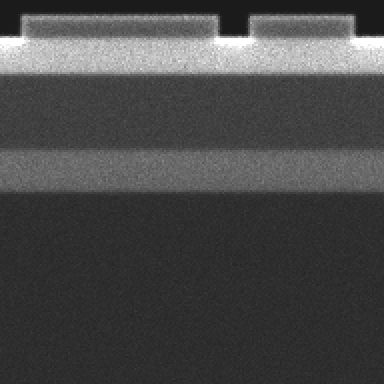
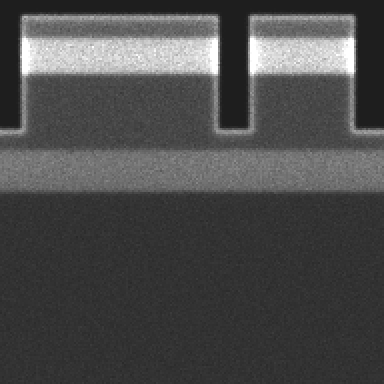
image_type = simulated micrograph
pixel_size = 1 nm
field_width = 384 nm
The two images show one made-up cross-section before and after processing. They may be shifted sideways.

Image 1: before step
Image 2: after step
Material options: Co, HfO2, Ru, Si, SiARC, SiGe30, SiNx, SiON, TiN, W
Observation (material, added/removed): HfO2 and SiNx, removed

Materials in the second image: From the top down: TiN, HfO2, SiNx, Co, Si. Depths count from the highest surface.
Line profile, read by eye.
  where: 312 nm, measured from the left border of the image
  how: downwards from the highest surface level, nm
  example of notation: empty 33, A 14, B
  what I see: TiN 22, HfO2 36, SiNx 76, Co 42, Si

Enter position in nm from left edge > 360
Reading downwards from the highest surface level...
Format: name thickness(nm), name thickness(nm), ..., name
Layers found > empty 114, SiNx 20, Co 42, Si